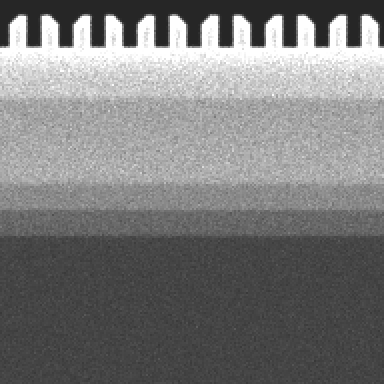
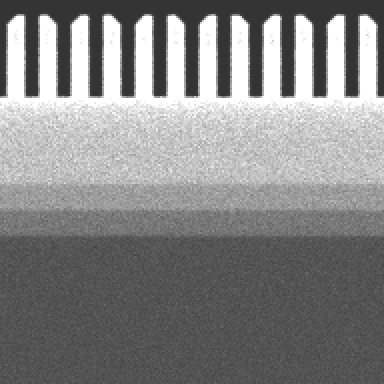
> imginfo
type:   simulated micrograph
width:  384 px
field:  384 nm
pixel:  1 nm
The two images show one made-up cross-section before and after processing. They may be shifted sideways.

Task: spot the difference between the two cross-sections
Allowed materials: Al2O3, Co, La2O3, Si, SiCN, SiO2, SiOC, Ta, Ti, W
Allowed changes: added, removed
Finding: removed W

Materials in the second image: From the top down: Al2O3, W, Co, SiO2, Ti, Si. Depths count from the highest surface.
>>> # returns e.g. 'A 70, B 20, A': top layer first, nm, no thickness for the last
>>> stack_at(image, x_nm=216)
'empty 82, Co 86, SiO2 26, Ti 26, Si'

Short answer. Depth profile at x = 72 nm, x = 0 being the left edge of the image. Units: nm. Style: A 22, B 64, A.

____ empty 8, Al2O3 24, W 50, Co 86, SiO2 26, Ti 26, Si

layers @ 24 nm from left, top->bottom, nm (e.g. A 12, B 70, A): empty 82, Co 86, SiO2 26, Ti 26, Si